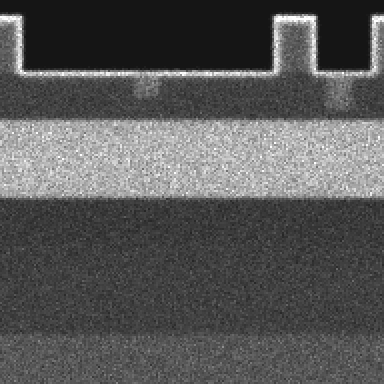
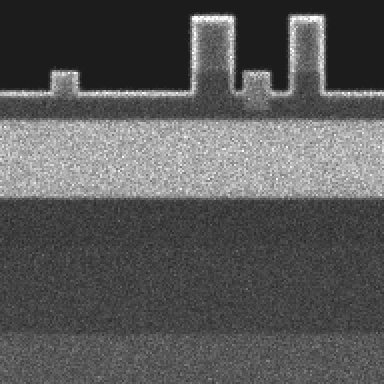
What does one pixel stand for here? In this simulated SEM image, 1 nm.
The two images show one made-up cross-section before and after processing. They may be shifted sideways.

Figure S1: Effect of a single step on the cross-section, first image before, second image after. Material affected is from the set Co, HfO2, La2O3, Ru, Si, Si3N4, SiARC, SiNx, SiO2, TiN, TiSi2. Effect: removed Si3N4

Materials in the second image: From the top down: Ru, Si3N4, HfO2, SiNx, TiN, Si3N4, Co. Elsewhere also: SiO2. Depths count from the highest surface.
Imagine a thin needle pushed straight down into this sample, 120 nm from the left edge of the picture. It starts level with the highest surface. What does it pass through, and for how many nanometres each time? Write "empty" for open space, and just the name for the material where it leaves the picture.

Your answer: empty 76, Si3N4 28, HfO2 78, SiNx 46, TiN 24, Si3N4 66, Co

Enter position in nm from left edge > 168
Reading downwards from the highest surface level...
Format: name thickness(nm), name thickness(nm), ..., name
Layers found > empty 76, Si3N4 28, HfO2 78, SiNx 46, TiN 24, Si3N4 66, Co